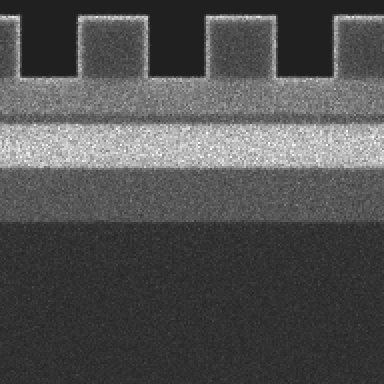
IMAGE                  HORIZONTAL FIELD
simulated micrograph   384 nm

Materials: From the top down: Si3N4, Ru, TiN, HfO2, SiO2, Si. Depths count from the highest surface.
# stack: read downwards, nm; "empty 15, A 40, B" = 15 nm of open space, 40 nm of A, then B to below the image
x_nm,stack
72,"empty 62, Ru 36, TiN 10, HfO2 44, SiO2 54, Si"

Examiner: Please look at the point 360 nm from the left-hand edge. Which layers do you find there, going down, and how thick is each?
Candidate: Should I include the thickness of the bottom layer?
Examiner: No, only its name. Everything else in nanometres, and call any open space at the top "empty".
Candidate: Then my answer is Si3N4 62, Ru 36, TiN 10, HfO2 44, SiO2 54, Si